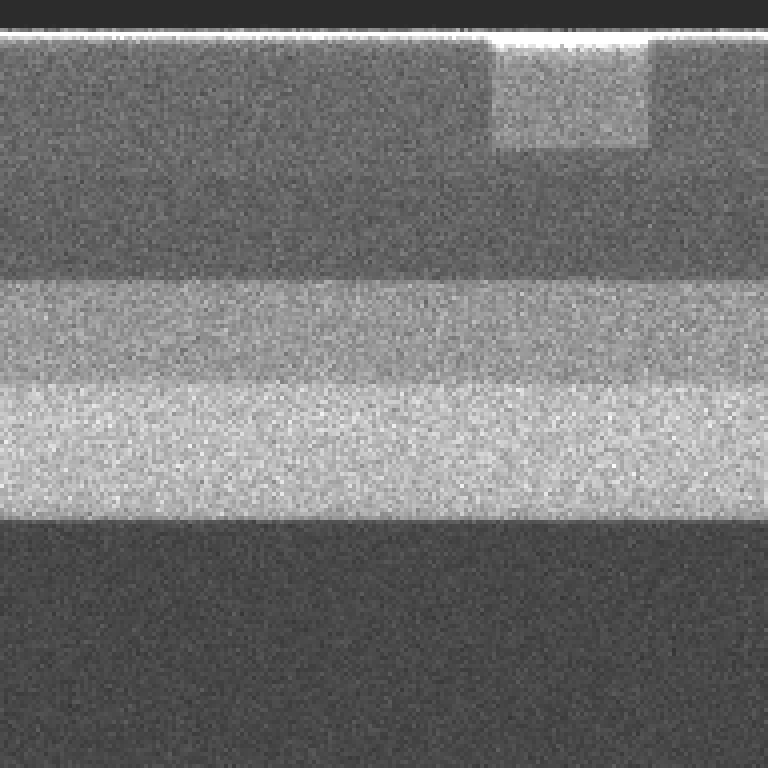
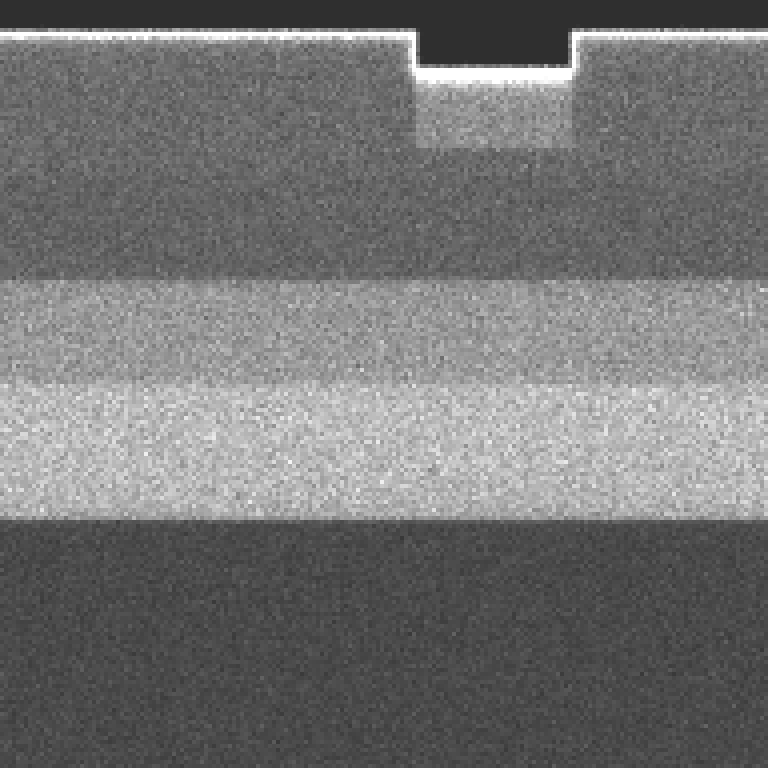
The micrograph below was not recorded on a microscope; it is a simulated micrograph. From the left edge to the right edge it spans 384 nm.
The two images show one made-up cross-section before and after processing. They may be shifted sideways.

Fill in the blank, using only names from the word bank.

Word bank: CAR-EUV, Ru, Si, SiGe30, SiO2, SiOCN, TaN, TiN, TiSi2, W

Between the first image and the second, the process removed SiO2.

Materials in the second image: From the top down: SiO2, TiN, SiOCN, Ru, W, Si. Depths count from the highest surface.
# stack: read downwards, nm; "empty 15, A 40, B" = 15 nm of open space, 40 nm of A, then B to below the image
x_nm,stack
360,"TiN 72, SiOCN 52, Ru 52, W 68, Si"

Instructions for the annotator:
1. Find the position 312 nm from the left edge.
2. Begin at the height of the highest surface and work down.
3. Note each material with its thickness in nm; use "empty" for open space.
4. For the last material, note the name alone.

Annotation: TiN 72, SiOCN 52, Ru 52, W 68, Si